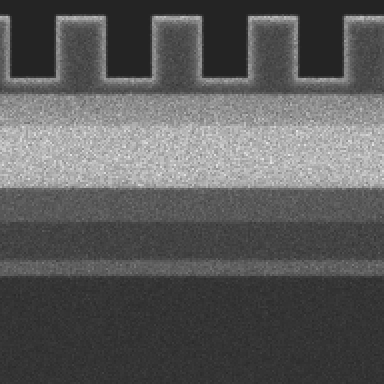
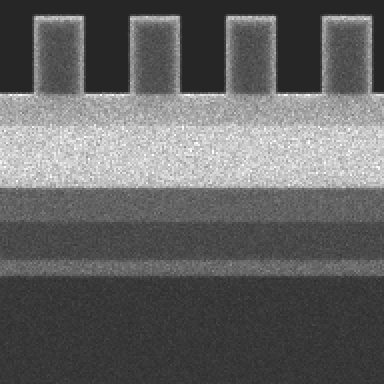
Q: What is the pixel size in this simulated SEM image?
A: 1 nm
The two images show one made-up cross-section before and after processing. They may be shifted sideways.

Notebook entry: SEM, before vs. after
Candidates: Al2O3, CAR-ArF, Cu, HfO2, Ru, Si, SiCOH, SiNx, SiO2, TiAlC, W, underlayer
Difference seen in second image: underlayer removed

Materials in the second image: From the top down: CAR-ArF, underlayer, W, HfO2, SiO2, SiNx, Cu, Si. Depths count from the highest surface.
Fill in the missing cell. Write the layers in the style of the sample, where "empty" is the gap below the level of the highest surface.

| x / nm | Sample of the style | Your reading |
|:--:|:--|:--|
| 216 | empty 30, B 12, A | empty 78, W 32, HfO2 62, SiO2 34, SiNx 38, Cu 16, Si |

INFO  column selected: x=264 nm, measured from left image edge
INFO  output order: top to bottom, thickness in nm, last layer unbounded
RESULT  CAR-ArF 62, underlayer 16, W 32, HfO2 62, SiO2 34, SiNx 38, Cu 16, Si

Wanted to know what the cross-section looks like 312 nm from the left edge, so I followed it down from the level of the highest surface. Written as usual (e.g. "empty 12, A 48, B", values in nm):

empty 78, W 32, HfO2 62, SiO2 34, SiNx 38, Cu 16, Si